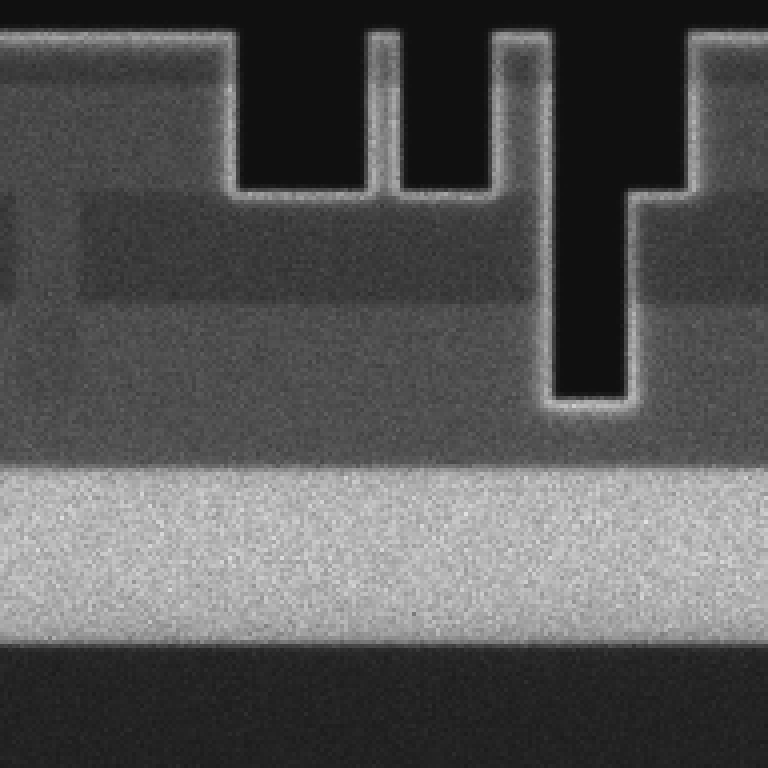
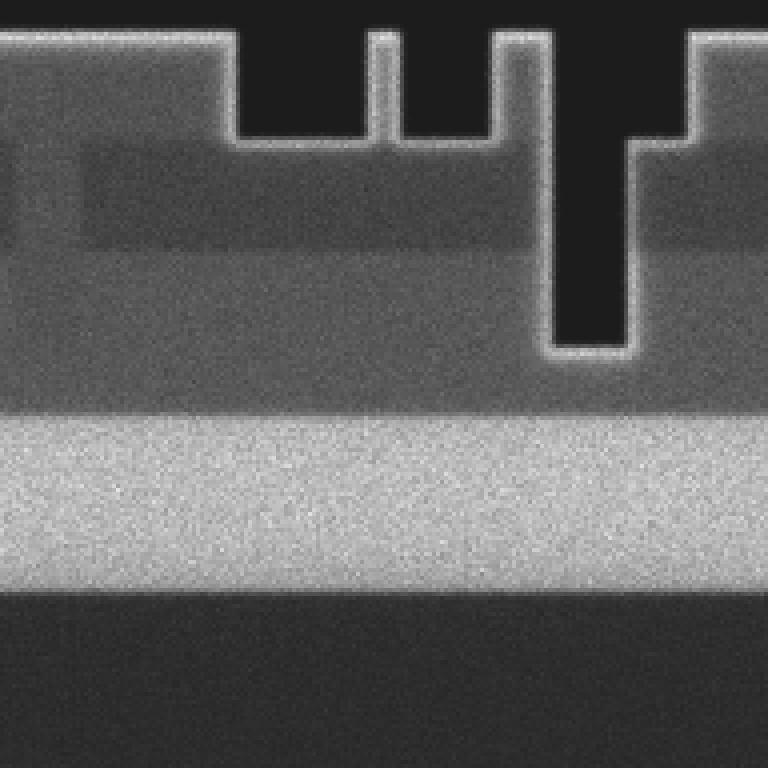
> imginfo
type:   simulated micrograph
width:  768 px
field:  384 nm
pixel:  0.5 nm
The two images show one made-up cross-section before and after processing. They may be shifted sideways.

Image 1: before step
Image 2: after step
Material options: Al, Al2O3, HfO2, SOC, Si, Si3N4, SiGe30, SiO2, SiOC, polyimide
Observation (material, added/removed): SOC, removed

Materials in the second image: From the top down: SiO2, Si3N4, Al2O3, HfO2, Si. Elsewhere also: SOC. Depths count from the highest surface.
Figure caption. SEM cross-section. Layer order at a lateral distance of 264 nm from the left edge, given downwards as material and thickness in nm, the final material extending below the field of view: SiO2 54, Si3N4 56, Al2O3 82, HfO2 88, Si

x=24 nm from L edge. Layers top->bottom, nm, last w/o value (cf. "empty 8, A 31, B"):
SiO2 158, Al2O3 34, HfO2 88, Si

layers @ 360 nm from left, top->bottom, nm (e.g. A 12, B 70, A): SiO2 54, Si3N4 56, Al2O3 82, HfO2 88, Si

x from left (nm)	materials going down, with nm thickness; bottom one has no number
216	empty 54, Si3N4 56, Al2O3 82, HfO2 88, Si